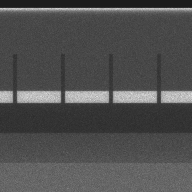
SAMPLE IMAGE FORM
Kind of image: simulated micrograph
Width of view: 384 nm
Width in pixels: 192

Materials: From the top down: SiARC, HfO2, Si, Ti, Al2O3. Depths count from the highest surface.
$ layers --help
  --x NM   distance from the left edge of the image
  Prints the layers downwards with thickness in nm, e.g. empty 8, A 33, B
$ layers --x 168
SiARC 166, HfO2 24, Si 60, Ti 60, Al2O3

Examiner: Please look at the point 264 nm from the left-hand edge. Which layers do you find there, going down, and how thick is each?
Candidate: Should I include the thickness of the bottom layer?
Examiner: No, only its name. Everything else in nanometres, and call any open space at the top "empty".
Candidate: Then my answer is SiARC 166, HfO2 24, Si 60, Ti 60, Al2O3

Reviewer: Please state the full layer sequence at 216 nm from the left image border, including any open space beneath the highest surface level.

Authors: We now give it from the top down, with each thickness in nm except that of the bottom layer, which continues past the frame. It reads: SiARC 166, HfO2 24, Si 60, Ti 60, Al2O3